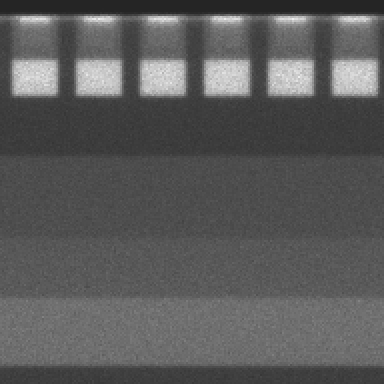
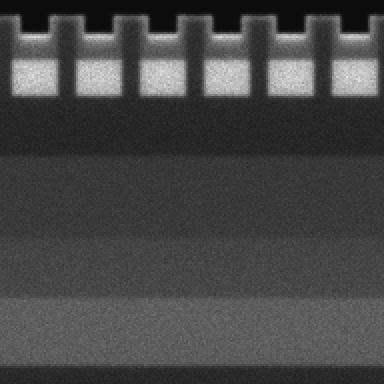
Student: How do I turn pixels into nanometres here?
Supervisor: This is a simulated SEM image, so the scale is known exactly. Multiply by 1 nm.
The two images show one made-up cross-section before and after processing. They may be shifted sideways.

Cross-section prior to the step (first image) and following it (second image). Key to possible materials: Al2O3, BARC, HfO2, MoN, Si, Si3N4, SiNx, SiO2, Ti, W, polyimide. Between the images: SiO2 was removed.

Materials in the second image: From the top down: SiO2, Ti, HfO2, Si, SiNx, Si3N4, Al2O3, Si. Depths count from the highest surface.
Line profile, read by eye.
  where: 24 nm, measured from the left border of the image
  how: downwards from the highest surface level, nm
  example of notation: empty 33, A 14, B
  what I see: empty 18, SiO2 12, Ti 14, HfO2 36, Si 60, SiNx 82, Si3N4 60, Al2O3 68, Si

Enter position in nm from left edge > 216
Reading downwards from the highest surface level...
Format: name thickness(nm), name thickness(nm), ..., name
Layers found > empty 18, SiO2 12, Ti 14, HfO2 36, Si 60, SiNx 82, Si3N4 60, Al2O3 68, Si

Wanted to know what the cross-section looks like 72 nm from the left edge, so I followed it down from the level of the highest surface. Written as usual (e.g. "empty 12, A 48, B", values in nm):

Si 140, SiNx 82, Si3N4 60, Al2O3 68, Si